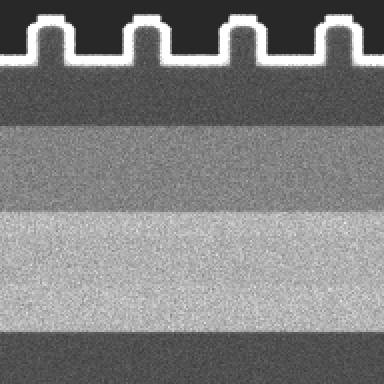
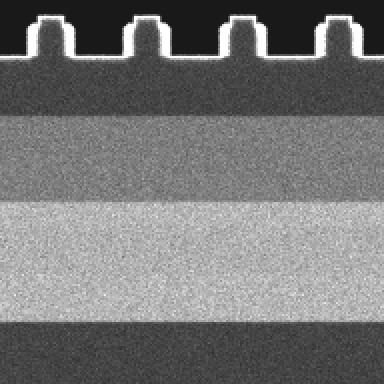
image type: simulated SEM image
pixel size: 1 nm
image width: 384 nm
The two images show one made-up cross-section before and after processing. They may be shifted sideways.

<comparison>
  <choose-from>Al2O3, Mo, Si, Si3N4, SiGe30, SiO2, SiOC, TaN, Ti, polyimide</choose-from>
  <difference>SiO2 removed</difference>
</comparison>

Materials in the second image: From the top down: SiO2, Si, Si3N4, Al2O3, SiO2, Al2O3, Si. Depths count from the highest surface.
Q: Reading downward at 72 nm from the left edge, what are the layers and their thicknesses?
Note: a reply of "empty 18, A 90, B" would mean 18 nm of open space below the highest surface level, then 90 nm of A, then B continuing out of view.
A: empty 12, SiO2 28, Si 60, Si3N4 86, Al2O3 24, SiO2 48, Al2O3 48, Si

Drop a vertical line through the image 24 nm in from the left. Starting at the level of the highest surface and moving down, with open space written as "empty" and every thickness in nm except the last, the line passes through empty 40, Si 60, Si3N4 86, Al2O3 24, SiO2 48, Al2O3 48, Si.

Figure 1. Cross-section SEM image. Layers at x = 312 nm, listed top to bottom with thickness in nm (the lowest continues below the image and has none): empty 40, Si 60, Si3N4 86, Al2O3 24, SiO2 48, Al2O3 48, Si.